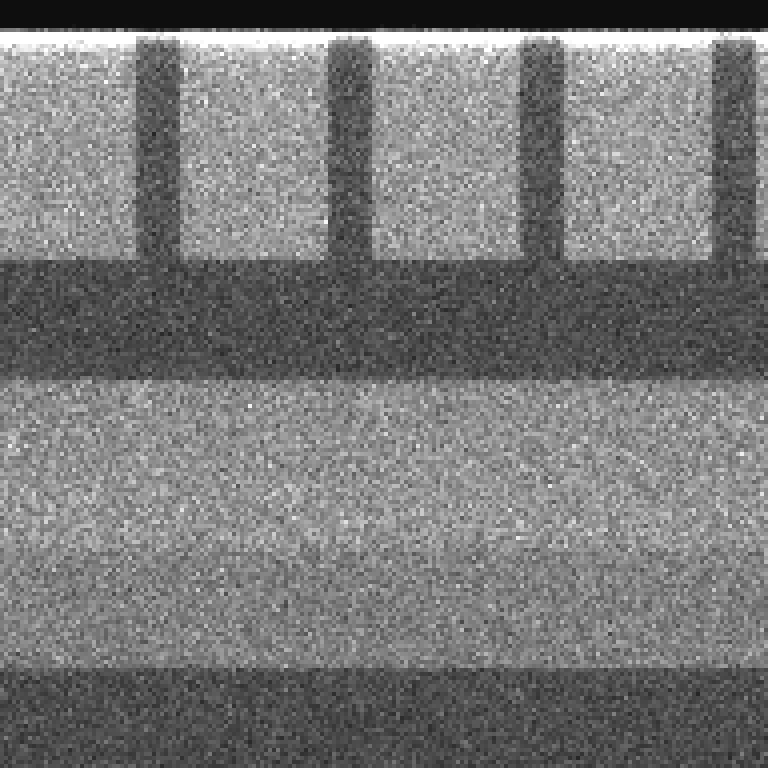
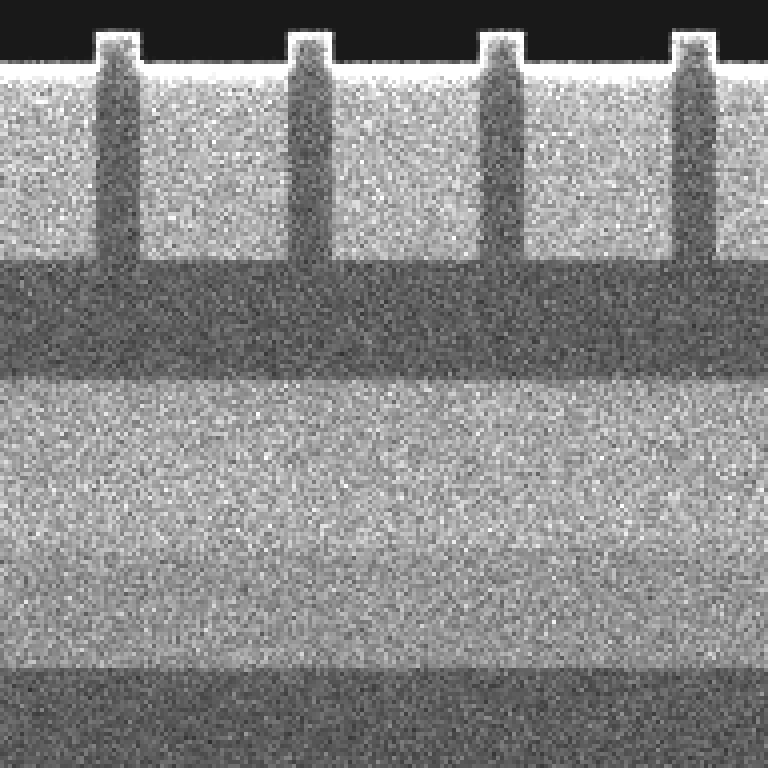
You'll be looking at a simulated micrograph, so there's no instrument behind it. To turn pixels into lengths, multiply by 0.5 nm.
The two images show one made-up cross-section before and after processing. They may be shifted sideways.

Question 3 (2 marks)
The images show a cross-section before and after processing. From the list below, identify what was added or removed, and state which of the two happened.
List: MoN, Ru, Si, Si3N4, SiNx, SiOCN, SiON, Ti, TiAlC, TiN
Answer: Si3N4 was removed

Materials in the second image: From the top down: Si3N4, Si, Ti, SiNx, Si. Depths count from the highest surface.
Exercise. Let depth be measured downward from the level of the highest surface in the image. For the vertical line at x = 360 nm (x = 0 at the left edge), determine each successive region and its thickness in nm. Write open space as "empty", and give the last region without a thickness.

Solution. empty 16, Si3N4 98, Si 60, Ti 84, SiNx 60, Si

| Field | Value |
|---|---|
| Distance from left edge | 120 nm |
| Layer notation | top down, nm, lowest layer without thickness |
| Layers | empty 16, Si3N4 98, Si 60, Ti 84, SiNx 60, Si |